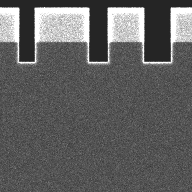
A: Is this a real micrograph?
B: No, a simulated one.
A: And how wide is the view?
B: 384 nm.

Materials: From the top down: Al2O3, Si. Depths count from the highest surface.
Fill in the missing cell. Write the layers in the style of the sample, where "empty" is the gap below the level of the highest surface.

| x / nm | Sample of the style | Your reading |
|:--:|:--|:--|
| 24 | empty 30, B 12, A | Al2O3 68, Si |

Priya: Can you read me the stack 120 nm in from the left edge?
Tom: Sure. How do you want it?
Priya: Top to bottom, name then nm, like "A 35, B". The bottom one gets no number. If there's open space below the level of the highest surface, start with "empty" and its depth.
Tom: Al2O3 68, Si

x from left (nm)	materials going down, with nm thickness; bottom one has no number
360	Al2O3 68, Si